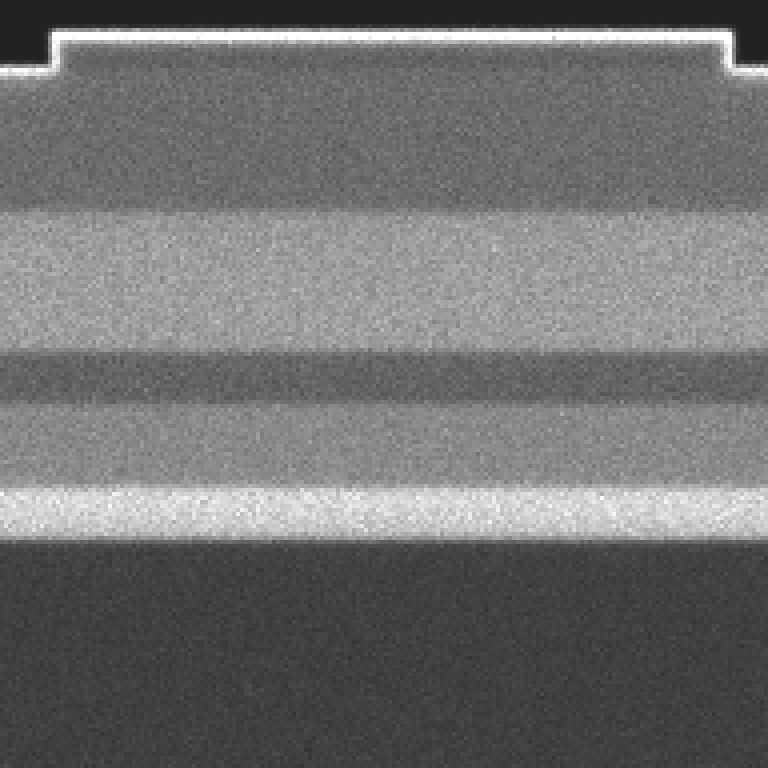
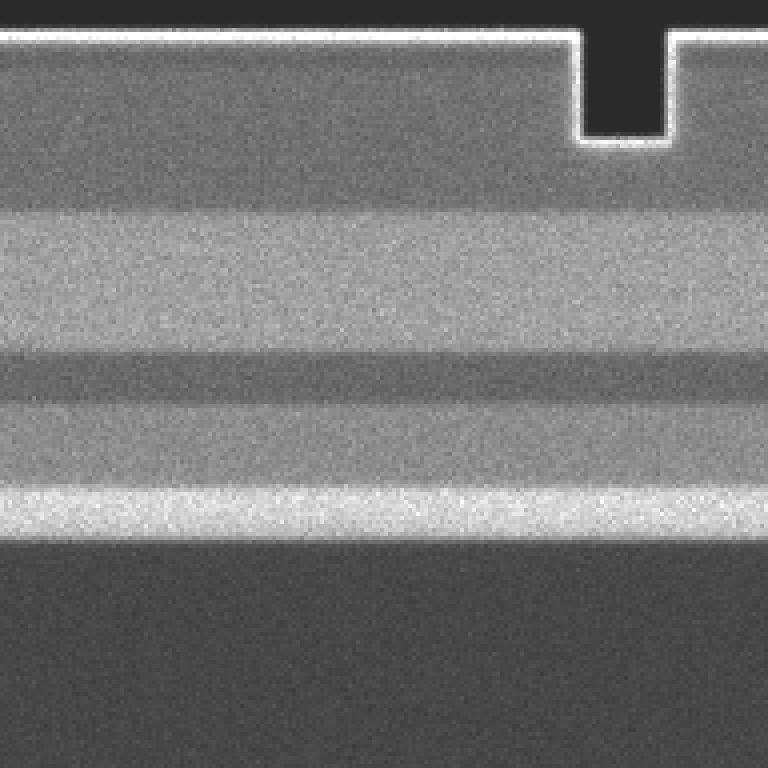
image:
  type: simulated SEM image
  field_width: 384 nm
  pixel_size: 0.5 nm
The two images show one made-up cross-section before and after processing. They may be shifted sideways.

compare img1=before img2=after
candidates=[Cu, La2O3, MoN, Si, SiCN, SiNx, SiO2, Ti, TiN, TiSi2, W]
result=removed:TiN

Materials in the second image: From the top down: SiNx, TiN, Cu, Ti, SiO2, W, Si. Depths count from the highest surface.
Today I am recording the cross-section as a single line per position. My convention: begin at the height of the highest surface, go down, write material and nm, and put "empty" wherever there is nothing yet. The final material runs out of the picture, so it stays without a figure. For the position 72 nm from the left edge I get SiNx 18, TiN 72, Cu 70, Ti 26, SiO2 42, W 26, Si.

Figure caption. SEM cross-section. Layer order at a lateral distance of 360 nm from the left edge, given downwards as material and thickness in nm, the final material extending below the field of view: SiNx 18, TiN 72, Cu 70, Ti 26, SiO2 42, W 26, Si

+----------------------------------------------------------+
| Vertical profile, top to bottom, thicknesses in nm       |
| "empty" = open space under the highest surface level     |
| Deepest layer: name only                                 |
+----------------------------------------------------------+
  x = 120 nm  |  SiNx 18, TiN 72, Cu 70, Ti 26, SiO2 42, W 26, Si